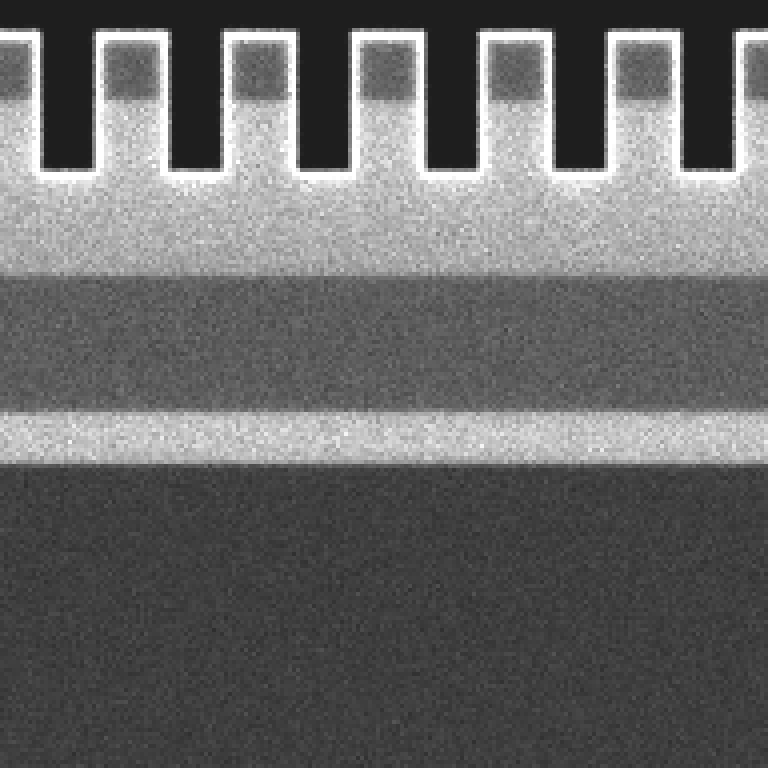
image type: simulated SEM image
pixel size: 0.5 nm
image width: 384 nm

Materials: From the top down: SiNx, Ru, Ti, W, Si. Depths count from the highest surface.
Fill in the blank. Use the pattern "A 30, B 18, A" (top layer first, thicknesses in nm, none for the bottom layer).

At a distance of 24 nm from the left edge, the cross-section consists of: empty 70, Ru 52, Ti 68, W 26, Si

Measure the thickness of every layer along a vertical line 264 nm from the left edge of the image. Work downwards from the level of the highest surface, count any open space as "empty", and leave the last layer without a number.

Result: SiNx 34, Ru 88, Ti 68, W 26, Si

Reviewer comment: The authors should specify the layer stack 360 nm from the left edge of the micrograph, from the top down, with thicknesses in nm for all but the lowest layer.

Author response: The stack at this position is empty 70, Ru 52, Ti 68, W 26, Si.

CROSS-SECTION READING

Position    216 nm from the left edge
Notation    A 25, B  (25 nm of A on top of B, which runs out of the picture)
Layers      empty 70, Ru 52, Ti 68, W 26, Si